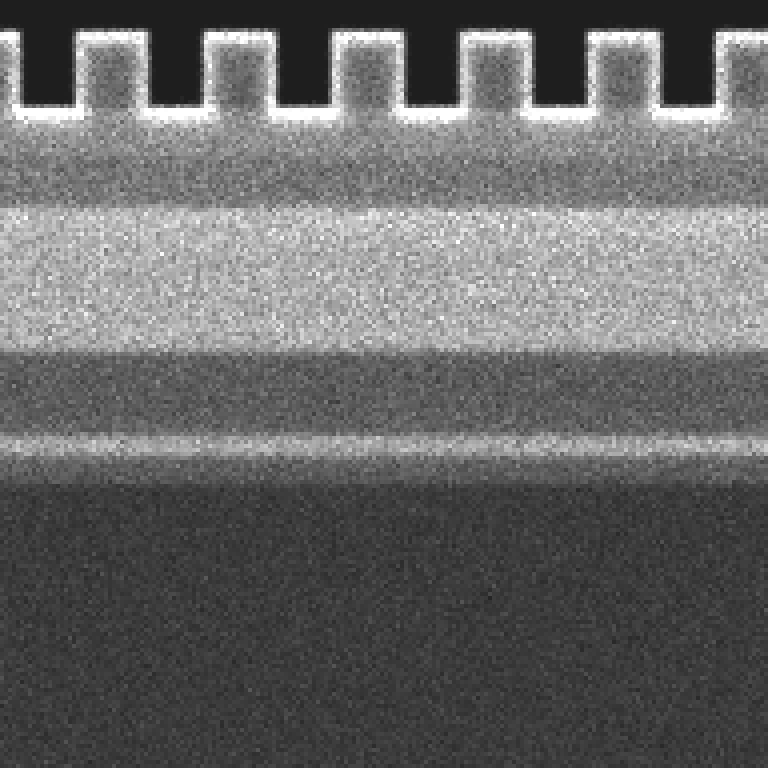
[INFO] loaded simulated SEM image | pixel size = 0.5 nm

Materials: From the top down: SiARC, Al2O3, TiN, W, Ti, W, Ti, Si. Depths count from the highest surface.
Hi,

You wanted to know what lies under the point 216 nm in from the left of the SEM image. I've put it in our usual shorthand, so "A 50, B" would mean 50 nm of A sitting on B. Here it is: empty 38, Al2O3 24, TiN 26, W 72, Ti 42, W 10, Ti 14, Si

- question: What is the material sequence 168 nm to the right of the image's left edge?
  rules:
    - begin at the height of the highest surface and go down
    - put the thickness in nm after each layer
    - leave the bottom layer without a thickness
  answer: SiARC 38, Al2O3 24, TiN 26, W 72, Ti 42, W 10, Ti 14, Si